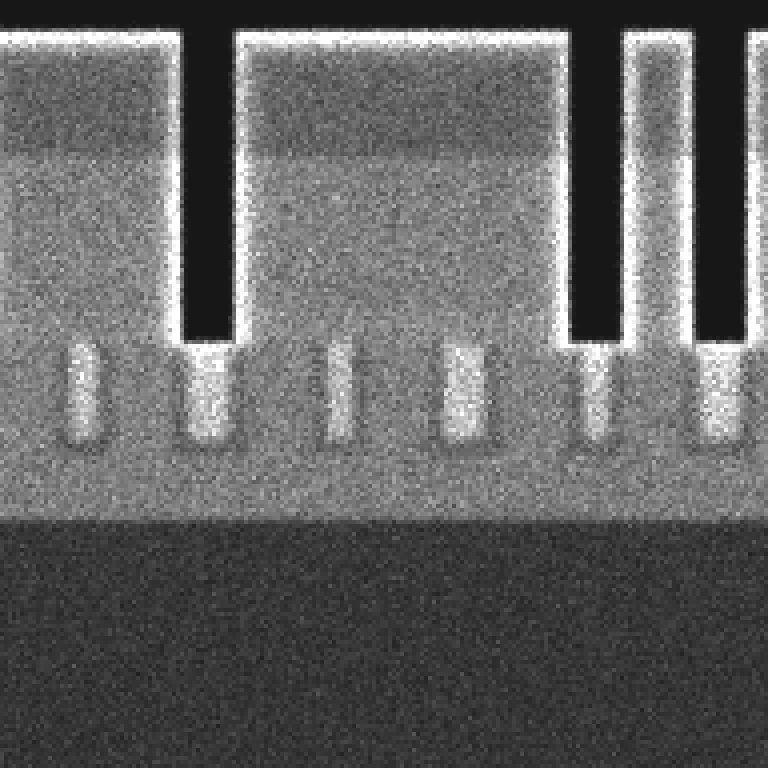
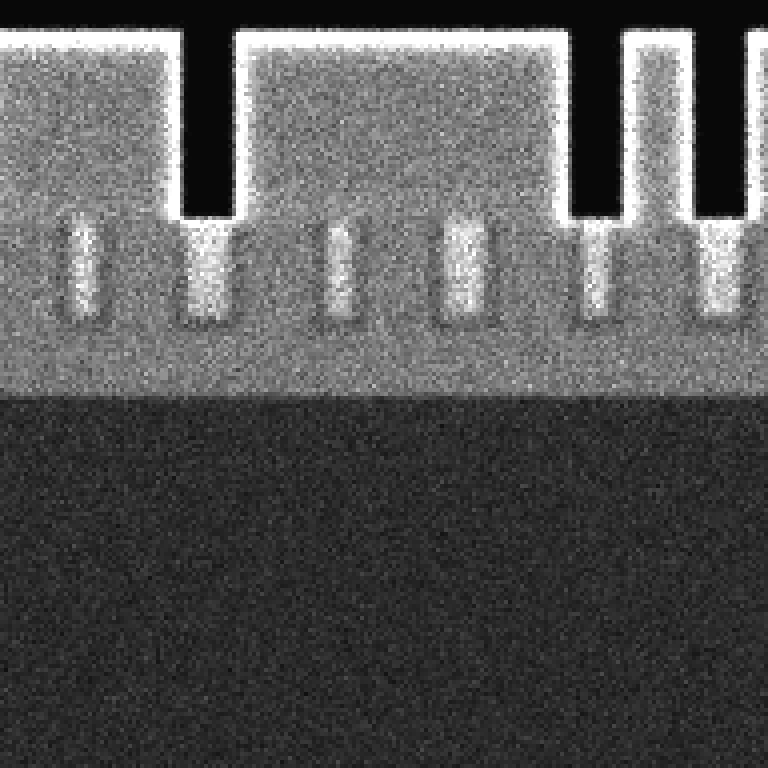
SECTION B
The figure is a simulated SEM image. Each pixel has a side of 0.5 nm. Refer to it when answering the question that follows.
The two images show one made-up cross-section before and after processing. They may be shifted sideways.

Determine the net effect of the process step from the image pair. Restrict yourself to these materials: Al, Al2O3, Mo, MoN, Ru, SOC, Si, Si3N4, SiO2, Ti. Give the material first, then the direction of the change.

SOC: removed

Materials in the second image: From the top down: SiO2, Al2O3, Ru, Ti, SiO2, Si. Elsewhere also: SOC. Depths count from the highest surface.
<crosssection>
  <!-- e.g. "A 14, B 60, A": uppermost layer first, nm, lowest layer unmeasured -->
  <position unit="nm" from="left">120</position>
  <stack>SiO2 78, Al2O3 16, Ti 56, SiO2 32, Si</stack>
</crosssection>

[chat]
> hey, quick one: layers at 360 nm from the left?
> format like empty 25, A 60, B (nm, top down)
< empty 94, Ru 48, Ti 8, SiO2 32, Si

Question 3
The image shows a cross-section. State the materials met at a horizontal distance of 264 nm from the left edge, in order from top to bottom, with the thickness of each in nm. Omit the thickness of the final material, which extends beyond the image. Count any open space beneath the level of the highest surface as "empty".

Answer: SiO2 78, Al2O3 16, SiO2 88, Si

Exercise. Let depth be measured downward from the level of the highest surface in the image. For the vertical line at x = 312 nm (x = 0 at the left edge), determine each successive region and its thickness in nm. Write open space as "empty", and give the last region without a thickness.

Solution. SiO2 78, Al2O3 16, SiO2 88, Si